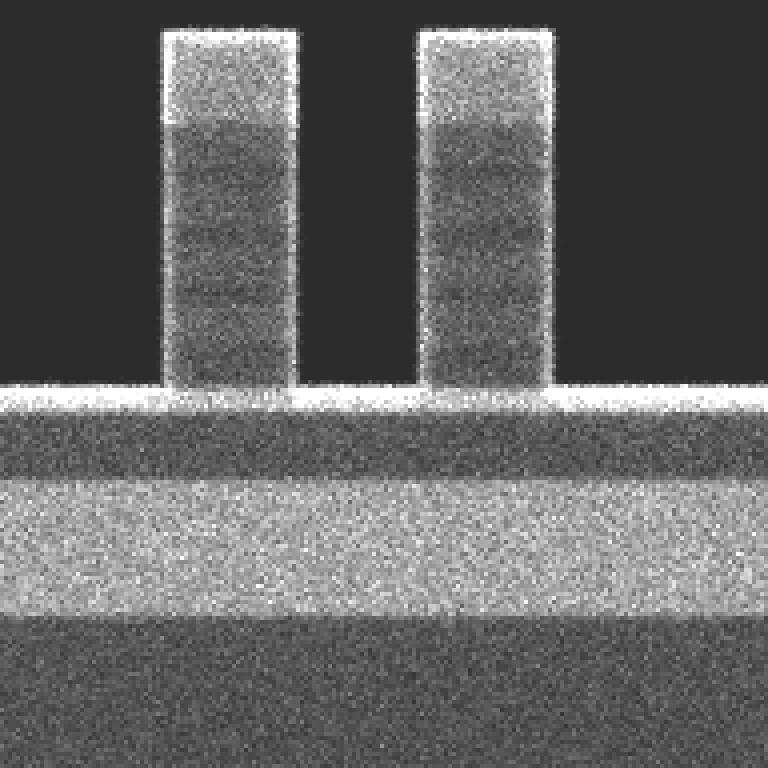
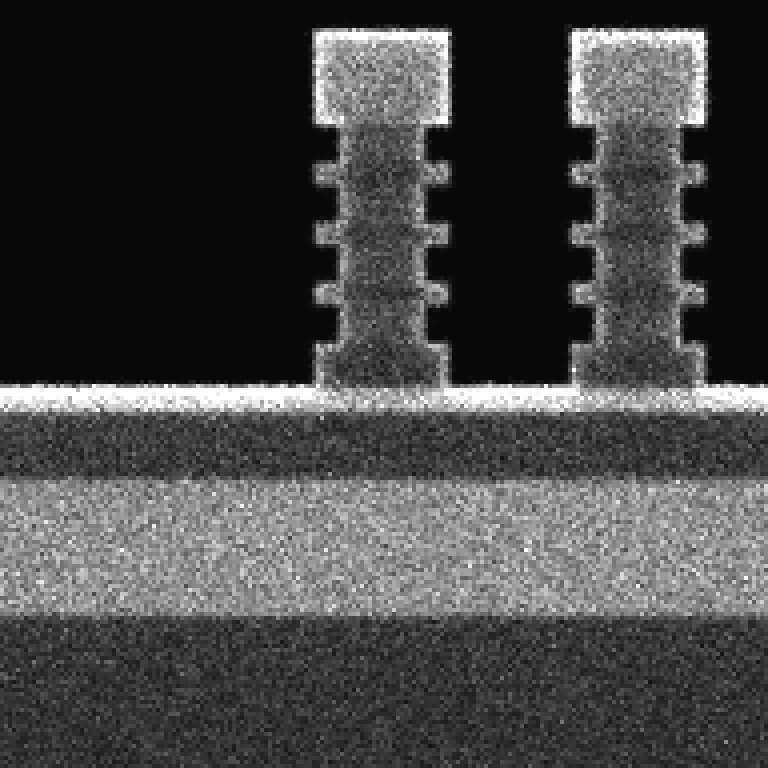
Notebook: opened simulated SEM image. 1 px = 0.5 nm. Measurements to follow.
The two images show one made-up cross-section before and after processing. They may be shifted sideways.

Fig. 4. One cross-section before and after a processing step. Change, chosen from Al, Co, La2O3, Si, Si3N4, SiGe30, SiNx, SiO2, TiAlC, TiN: SiGe30 removed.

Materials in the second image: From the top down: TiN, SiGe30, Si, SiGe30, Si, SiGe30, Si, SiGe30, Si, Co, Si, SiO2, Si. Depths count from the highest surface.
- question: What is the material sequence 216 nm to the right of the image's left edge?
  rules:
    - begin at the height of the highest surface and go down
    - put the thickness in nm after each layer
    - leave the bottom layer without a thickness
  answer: TiN 46, empty 20, Si 10, empty 20, Si 10, empty 20, Si 10, empty 20, Si 22, Co 12, Si 34, SiO2 68, Si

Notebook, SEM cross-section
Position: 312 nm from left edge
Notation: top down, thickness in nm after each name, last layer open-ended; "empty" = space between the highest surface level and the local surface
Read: TiN 46, SiGe30 20, Si 10, SiGe30 20, Si 10, SiGe30 20, Si 10, SiGe30 20, Si 22, Co 12, Si 34, SiO2 68, Si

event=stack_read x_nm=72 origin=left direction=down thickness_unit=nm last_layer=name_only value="empty 178, Co 12, Si 34, SiO2 68, Si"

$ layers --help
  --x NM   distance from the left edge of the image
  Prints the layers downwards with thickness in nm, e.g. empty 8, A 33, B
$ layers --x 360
empty 178, Co 12, Si 34, SiO2 68, Si